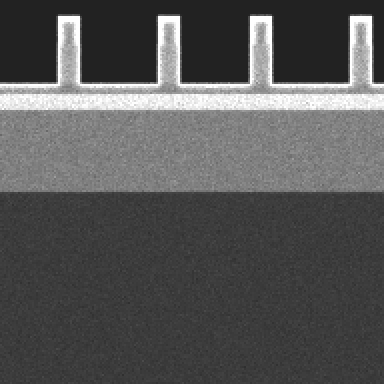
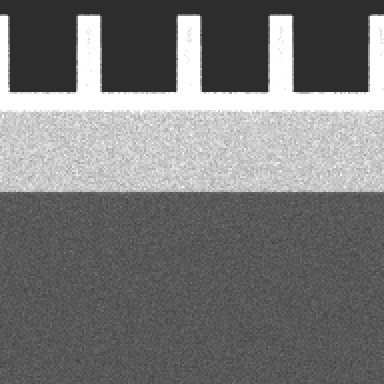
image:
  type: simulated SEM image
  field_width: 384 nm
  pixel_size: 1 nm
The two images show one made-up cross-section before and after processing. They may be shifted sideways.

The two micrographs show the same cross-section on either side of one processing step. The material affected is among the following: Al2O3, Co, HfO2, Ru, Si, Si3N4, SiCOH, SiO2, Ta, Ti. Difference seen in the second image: Co removed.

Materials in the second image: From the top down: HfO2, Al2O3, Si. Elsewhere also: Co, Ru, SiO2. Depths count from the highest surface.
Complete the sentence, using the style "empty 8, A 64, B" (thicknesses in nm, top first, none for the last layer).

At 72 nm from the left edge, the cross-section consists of empty 78, HfO2 16, Al2O3 82, Si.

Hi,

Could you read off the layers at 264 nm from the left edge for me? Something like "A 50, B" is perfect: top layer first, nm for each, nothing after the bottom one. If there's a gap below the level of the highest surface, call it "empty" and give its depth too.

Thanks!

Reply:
empty 78, HfO2 16, Al2O3 82, Si